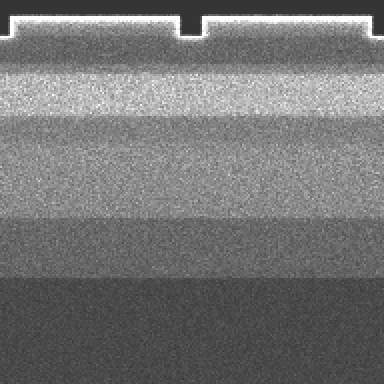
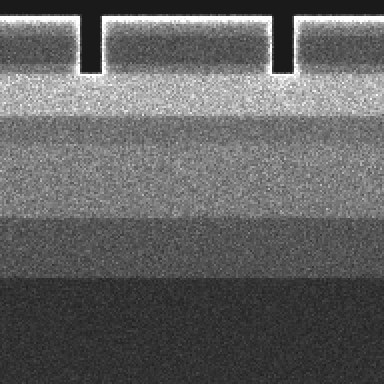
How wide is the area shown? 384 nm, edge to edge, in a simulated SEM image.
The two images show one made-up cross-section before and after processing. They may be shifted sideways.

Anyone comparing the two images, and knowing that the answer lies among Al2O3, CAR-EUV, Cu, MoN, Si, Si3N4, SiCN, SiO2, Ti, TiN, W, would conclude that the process removed Al2O3 and Si3N4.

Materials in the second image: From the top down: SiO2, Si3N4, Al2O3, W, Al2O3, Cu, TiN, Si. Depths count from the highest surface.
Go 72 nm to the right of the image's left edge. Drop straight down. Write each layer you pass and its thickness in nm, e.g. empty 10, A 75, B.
SiO2 20, Si3N4 28, Al2O3 10, W 42, Al2O3 28, Cu 74, TiN 60, Si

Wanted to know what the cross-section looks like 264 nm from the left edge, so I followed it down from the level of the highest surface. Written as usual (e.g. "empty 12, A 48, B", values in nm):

SiO2 20, Si3N4 28, Al2O3 10, W 42, Al2O3 28, Cu 74, TiN 60, Si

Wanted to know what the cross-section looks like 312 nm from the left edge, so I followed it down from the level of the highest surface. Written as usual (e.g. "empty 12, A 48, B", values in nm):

SiO2 20, Si3N4 28, Al2O3 10, W 42, Al2O3 28, Cu 74, TiN 60, Si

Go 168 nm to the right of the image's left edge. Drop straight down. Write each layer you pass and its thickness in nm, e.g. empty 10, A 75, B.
SiO2 20, Si3N4 28, Al2O3 10, W 42, Al2O3 28, Cu 74, TiN 60, Si